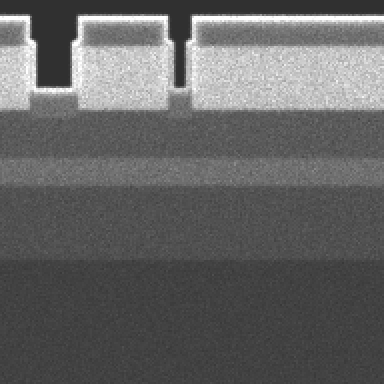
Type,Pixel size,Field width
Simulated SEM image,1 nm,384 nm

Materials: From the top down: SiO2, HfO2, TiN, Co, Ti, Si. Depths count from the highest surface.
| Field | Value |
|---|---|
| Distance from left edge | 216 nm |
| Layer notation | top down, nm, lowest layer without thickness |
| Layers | SiO2 30, HfO2 64, TiN 48, Co 28, Ti 74, Si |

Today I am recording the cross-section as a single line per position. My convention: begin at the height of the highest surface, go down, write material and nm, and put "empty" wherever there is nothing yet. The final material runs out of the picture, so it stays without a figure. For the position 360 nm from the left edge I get SiO2 30, HfO2 64, TiN 48, Co 28, Ti 74, Si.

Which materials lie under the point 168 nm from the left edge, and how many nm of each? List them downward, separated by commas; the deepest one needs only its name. empty 24, SiO2 78, TiN 40, Co 28, Ti 74, Si